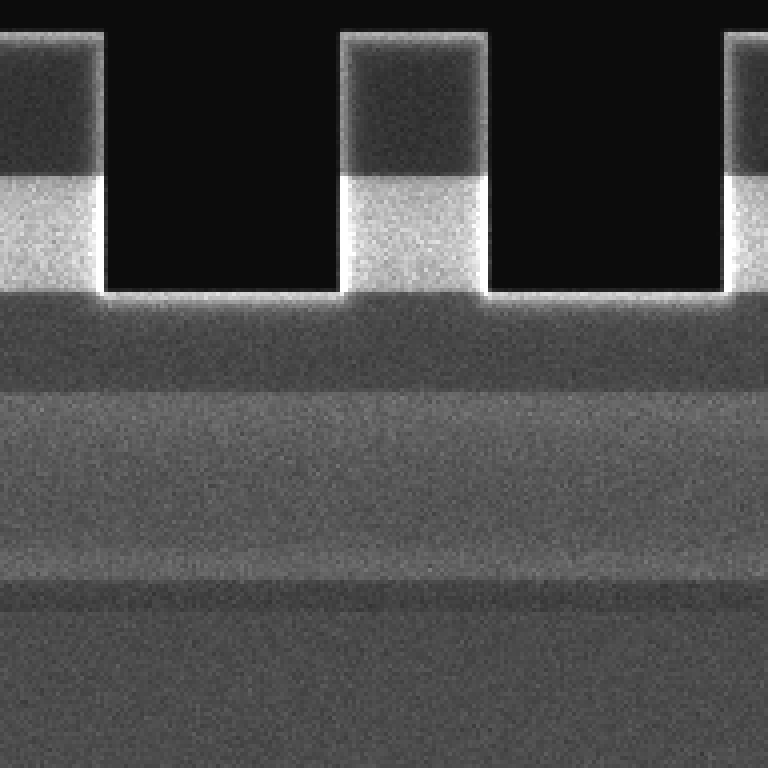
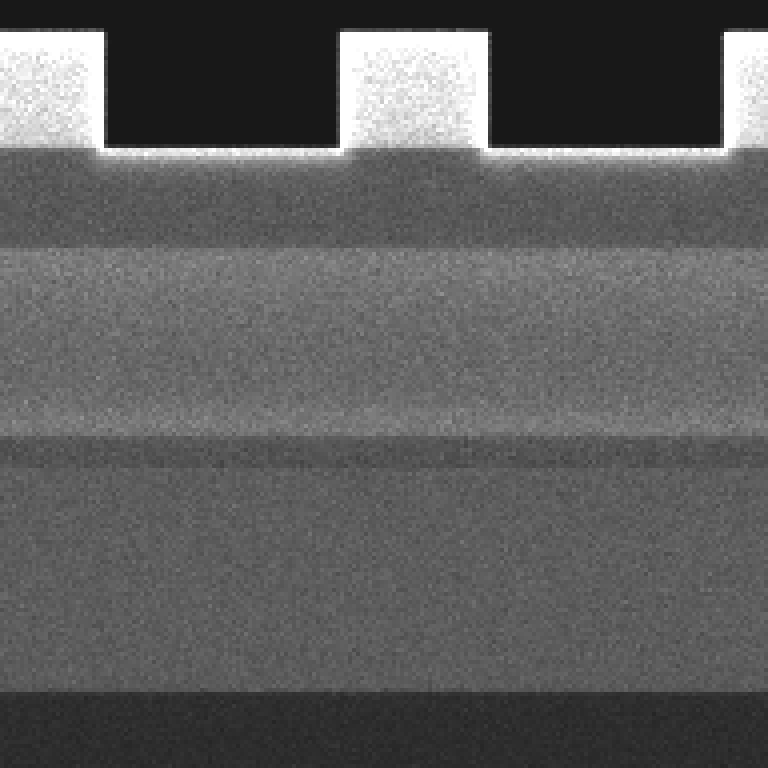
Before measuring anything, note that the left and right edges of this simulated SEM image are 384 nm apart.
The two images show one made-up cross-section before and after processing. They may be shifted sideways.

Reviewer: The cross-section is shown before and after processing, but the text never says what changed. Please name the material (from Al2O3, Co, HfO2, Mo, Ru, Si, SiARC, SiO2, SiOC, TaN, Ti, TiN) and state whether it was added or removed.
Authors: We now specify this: SiARC, removed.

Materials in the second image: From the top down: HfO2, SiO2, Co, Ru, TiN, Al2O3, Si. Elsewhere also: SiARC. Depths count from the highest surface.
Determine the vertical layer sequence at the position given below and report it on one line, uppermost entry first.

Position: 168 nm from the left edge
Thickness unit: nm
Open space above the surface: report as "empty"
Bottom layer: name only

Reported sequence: empty 58, SiO2 50, Co 80, Ru 14, TiN 16, Al2O3 112, Si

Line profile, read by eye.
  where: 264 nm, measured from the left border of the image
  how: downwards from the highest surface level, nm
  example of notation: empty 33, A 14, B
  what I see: empty 58, SiO2 50, Co 80, Ru 14, TiN 16, Al2O3 112, Si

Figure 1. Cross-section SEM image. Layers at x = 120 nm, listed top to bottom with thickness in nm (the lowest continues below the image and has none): empty 58, SiO2 50, Co 80, Ru 14, TiN 16, Al2O3 112, Si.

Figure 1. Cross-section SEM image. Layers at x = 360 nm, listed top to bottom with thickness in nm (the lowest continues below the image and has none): empty 58, SiO2 50, Co 80, Ru 14, TiN 16, Al2O3 112, Si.